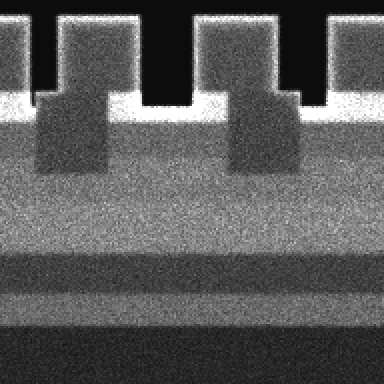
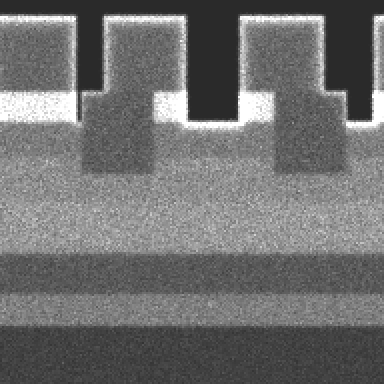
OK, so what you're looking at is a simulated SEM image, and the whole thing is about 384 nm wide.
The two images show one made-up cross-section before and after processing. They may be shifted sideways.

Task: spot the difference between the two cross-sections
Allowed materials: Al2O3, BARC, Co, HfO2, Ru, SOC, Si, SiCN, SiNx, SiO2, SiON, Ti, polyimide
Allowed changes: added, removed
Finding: removed HfO2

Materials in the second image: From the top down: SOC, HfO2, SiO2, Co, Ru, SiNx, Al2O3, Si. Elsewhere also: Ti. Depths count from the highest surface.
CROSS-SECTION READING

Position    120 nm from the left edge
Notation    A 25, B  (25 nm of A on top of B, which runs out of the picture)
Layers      SOC 76, Ti 82, Co 28, Ru 52, SiNx 40, Al2O3 32, Si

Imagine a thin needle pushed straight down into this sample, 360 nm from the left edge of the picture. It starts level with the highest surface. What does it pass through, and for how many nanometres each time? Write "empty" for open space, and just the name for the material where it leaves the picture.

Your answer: empty 106, SiO2 36, Co 44, Ru 52, SiNx 40, Al2O3 32, Si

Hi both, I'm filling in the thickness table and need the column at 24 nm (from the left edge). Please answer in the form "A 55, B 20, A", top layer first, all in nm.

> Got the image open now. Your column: SOC 76, HfO2 30, SiO2 36, Co 44, Ru 52, SiNx 40, Al2O3 32, Si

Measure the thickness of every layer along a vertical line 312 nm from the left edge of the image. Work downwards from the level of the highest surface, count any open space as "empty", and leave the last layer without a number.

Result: SOC 76, Ti 82, Co 28, Ru 52, SiNx 40, Al2O3 32, Si